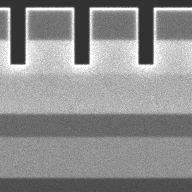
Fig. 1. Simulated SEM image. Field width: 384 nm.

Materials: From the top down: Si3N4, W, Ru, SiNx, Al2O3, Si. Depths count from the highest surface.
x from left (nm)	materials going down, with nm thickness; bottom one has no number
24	empty 114, W 18, Ru 80, SiNx 46, Al2O3 82, Si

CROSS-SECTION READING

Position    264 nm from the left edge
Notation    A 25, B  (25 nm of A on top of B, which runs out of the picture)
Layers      Si3N4 64, W 68, Ru 80, SiNx 46, Al2O3 82, Si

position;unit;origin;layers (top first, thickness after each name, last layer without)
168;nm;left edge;empty 114, W 18, Ru 80, SiNx 46, Al2O3 82, Si